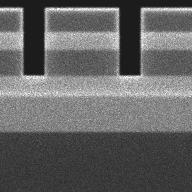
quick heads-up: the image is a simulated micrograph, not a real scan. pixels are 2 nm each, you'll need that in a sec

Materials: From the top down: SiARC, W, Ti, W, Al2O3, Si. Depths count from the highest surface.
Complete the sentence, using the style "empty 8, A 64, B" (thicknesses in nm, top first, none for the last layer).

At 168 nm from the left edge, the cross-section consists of SiARC 48, W 36, Ti 52, W 40, Al2O3 72, Si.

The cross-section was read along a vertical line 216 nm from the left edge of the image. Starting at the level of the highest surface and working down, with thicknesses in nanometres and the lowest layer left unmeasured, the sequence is SiARC 48, W 36, Ti 52, W 40, Al2O3 72, Si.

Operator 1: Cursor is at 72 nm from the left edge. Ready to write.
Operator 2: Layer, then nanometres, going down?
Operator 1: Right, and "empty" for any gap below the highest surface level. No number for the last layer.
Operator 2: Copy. empty 136, W 40, Al2O3 72, Si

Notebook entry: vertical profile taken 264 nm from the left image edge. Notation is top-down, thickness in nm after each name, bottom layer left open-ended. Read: empty 136, W 40, Al2O3 72, Si